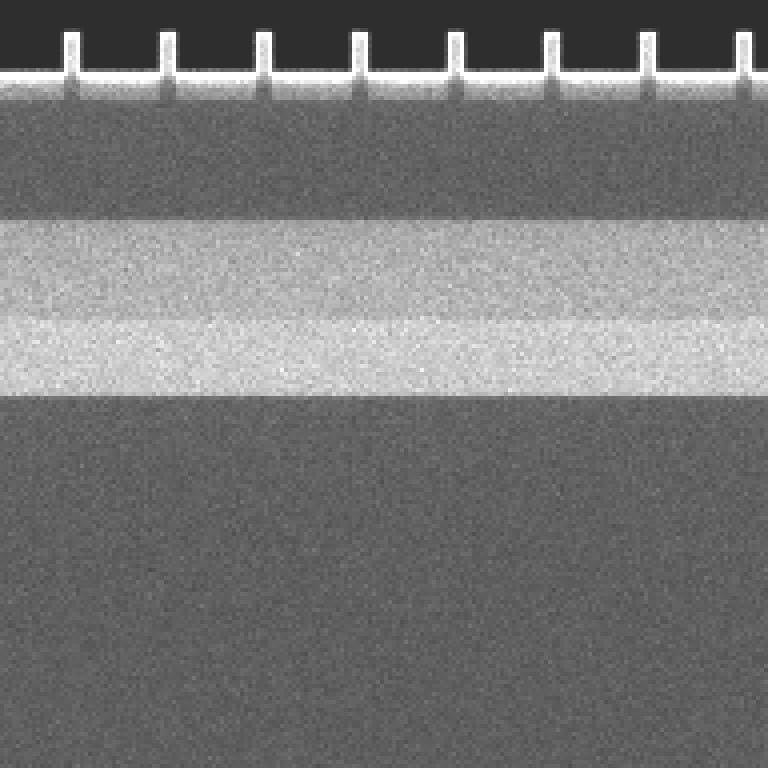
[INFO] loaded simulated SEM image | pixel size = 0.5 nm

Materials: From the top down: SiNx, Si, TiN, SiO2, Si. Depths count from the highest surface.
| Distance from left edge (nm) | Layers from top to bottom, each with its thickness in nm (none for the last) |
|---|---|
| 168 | empty 20, SiNx 14, Si 60, TiN 50, SiO2 38, Si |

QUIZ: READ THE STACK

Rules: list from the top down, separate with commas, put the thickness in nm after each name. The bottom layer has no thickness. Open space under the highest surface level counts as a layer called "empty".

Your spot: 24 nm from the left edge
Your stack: empty 20, SiNx 14, Si 60, TiN 50, SiO2 38, Si